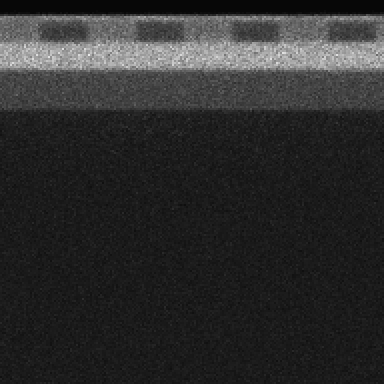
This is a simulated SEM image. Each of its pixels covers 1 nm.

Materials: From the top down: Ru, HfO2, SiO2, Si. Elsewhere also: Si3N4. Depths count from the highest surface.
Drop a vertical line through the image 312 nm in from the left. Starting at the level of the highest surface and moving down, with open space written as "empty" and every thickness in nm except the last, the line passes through Ru 26, HfO2 28, SiO2 40, Si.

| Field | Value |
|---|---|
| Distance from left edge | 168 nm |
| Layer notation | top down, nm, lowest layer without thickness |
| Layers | Si3N4 26, HfO2 28, SiO2 40, Si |